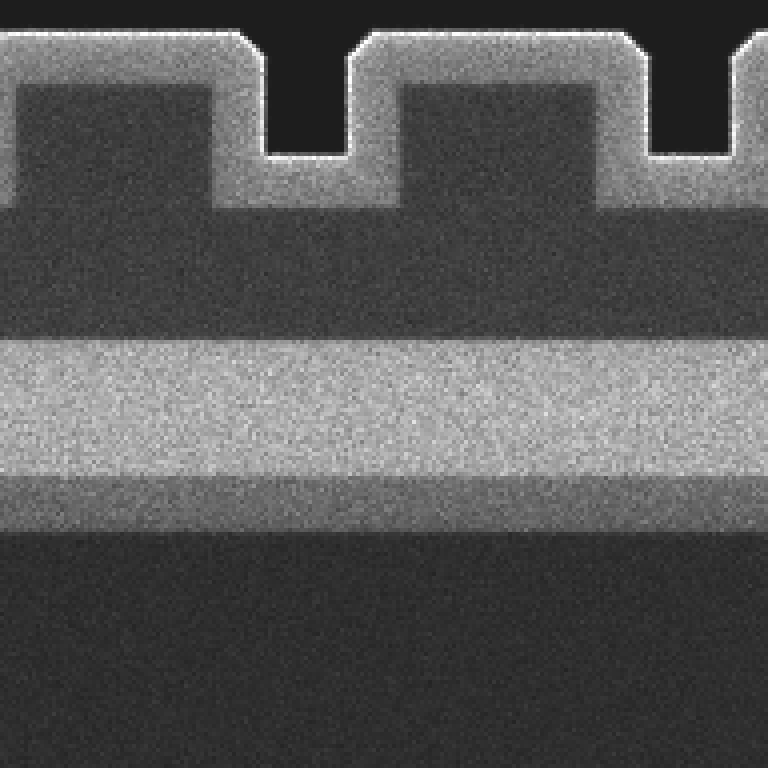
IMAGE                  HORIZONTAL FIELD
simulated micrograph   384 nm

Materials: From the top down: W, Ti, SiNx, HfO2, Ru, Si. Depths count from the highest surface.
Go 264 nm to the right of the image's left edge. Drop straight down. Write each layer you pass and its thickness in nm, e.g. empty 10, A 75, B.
W 26, Ti 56, SiNx 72, HfO2 68, Ru 28, Si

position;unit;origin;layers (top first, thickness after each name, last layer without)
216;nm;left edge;W 26, Ti 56, SiNx 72, HfO2 68, Ru 28, Si